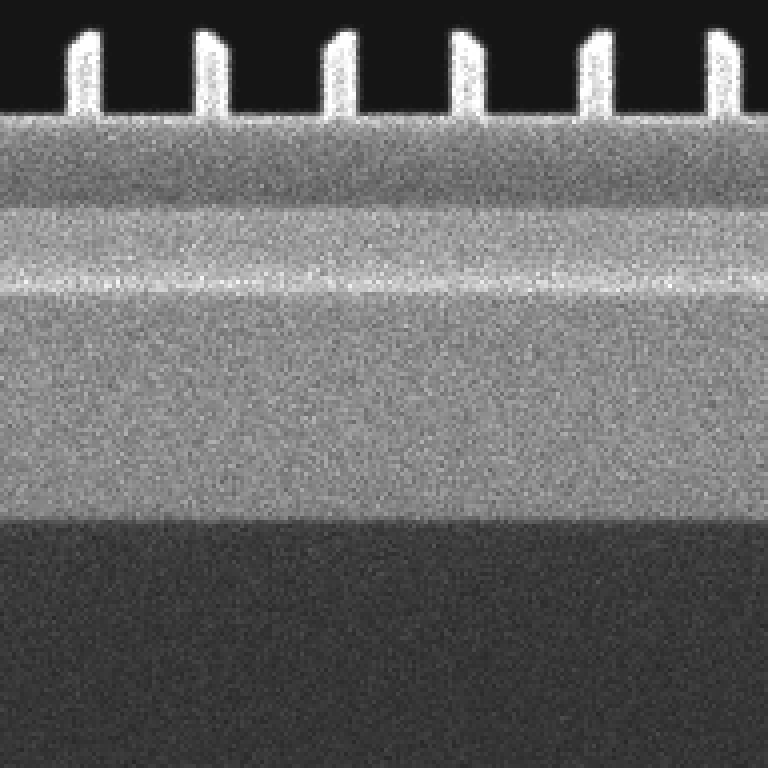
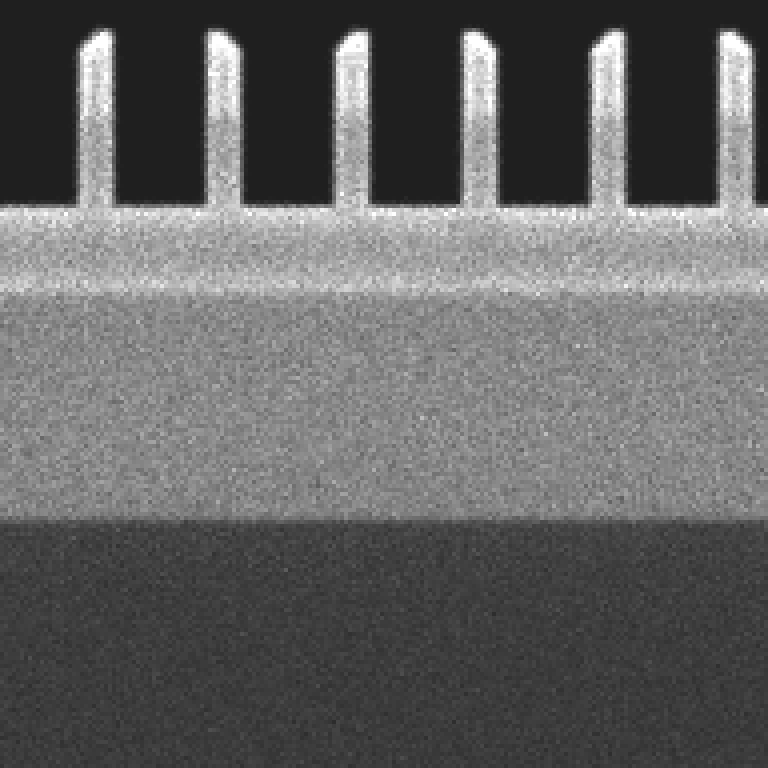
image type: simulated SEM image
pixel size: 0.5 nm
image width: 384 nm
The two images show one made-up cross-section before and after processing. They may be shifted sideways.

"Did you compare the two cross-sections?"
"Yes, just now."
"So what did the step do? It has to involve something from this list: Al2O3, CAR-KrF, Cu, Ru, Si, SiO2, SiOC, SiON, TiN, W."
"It removed TiN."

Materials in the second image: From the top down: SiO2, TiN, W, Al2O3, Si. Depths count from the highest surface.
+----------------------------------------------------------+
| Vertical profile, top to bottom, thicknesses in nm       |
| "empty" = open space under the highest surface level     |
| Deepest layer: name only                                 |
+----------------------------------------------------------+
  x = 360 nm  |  SiO2 42, TiN 46, W 42, Al2O3 114, Si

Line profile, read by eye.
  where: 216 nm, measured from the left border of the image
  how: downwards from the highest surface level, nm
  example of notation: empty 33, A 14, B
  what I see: empty 88, W 42, Al2O3 114, Si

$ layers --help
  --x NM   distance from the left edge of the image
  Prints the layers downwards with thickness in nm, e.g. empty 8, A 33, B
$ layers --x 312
empty 88, W 42, Al2O3 114, Si